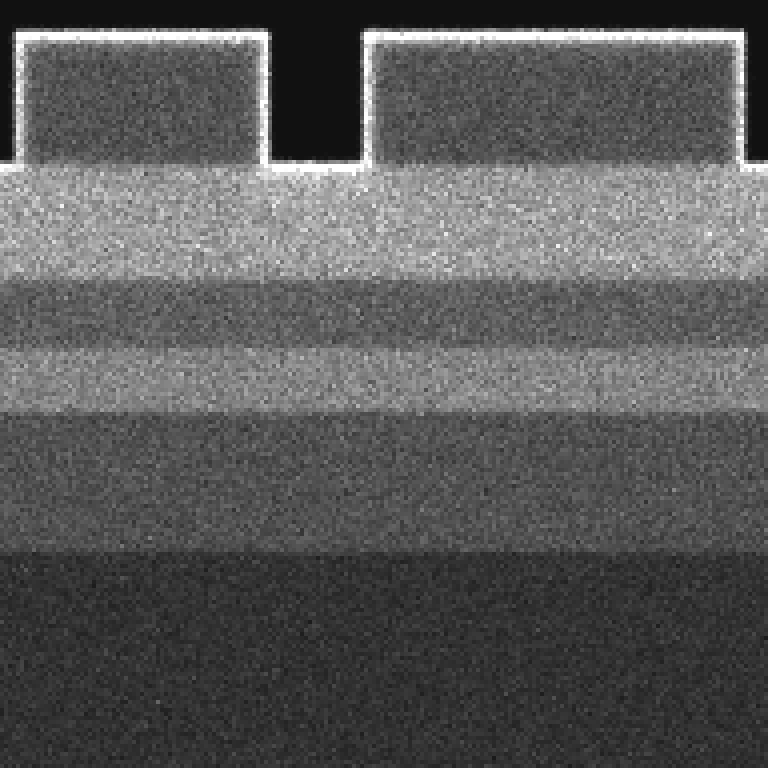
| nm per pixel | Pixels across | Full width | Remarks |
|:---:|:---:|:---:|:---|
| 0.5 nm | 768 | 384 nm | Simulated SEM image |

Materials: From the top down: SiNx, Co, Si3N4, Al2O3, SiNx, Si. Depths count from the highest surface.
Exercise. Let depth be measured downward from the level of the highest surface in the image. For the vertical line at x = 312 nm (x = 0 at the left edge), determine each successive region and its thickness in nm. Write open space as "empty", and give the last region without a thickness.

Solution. SiNx 66, Co 58, Si3N4 34, Al2O3 32, SiNx 70, Si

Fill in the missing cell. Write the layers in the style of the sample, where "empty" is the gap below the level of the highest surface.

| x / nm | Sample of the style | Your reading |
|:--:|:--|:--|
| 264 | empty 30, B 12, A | SiNx 66, Co 58, Si3N4 34, Al2O3 32, SiNx 70, Si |